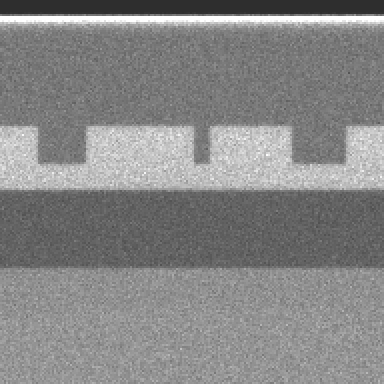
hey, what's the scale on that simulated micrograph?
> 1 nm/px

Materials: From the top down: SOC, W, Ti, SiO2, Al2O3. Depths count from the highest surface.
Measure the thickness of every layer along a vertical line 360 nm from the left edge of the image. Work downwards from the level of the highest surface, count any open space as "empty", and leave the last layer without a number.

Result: SOC 110, W 64, Ti 78, SiO2 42, Al2O3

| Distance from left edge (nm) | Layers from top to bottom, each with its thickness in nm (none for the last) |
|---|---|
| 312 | SOC 148, W 26, Ti 78, SiO2 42, Al2O3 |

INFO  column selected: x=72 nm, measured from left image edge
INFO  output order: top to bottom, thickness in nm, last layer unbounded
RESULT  SOC 148, W 26, Ti 78, SiO2 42, Al2O3